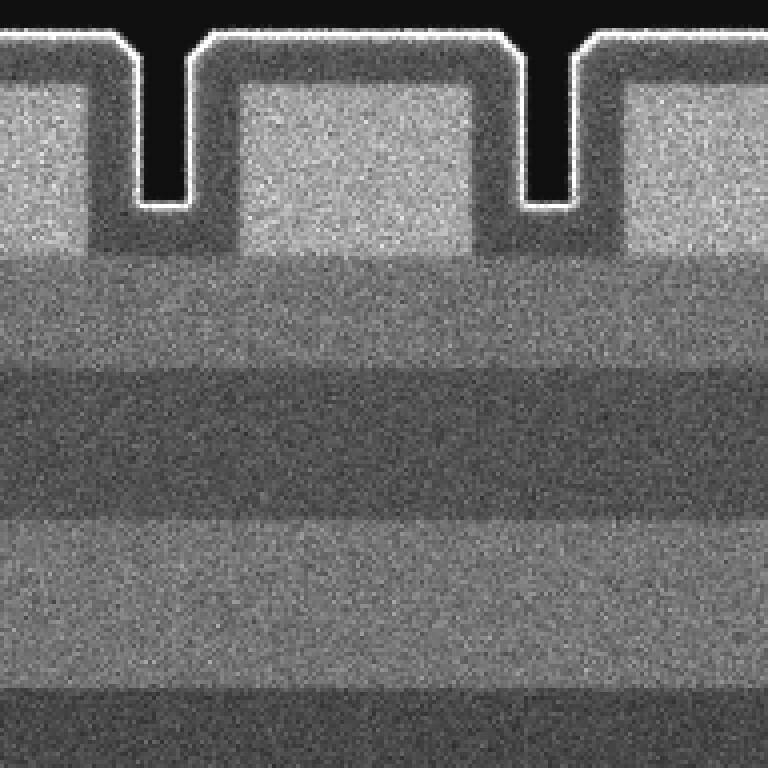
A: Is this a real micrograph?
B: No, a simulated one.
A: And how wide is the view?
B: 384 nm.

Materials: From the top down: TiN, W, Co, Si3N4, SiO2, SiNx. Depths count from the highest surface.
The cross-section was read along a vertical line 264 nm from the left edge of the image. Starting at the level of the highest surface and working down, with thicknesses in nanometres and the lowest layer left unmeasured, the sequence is empty 86, TiN 26, Co 56, Si3N4 76, SiO2 84, SiNx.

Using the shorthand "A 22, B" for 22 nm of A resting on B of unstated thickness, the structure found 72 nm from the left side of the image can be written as empty 86, TiN 26, Co 56, Si3N4 76, SiO2 84, SiNx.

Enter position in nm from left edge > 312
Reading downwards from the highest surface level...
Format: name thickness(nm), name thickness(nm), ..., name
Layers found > TiN 26, W 86, Co 56, Si3N4 76, SiO2 84, SiNx